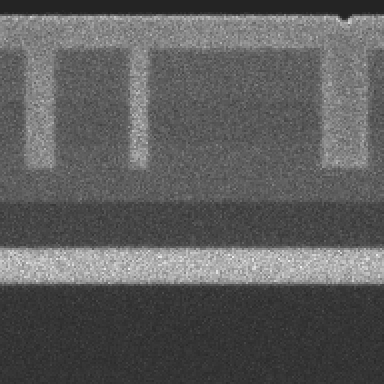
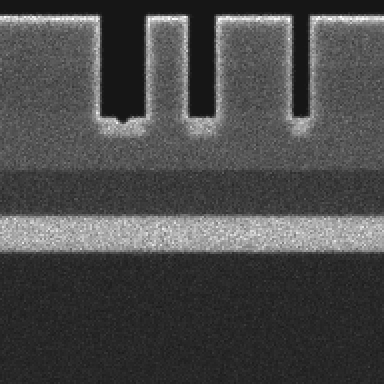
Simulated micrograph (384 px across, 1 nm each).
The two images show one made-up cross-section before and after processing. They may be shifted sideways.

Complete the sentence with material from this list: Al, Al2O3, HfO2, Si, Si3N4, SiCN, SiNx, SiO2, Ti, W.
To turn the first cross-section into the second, W must be removed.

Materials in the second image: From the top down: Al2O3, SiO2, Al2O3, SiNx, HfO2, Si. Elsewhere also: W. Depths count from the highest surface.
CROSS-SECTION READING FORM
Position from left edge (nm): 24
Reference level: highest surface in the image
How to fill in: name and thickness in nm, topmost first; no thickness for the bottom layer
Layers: Al2O3 52, SiO2 44, Al2O3 58, SiNx 46, HfO2 36, Si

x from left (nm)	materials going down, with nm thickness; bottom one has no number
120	empty 108, W 12, Al2O3 34, SiNx 46, HfO2 36, Si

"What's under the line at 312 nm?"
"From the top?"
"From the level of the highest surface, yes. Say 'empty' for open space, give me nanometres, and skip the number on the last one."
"Al2O3 52, SiO2 44, Al2O3 58, SiNx 46, HfO2 36, Si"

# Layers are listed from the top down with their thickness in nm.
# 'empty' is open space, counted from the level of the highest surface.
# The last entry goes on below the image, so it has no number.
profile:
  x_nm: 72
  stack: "Al2O3 52, SiO2 44, Al2O3 58, SiNx 46, HfO2 36, Si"